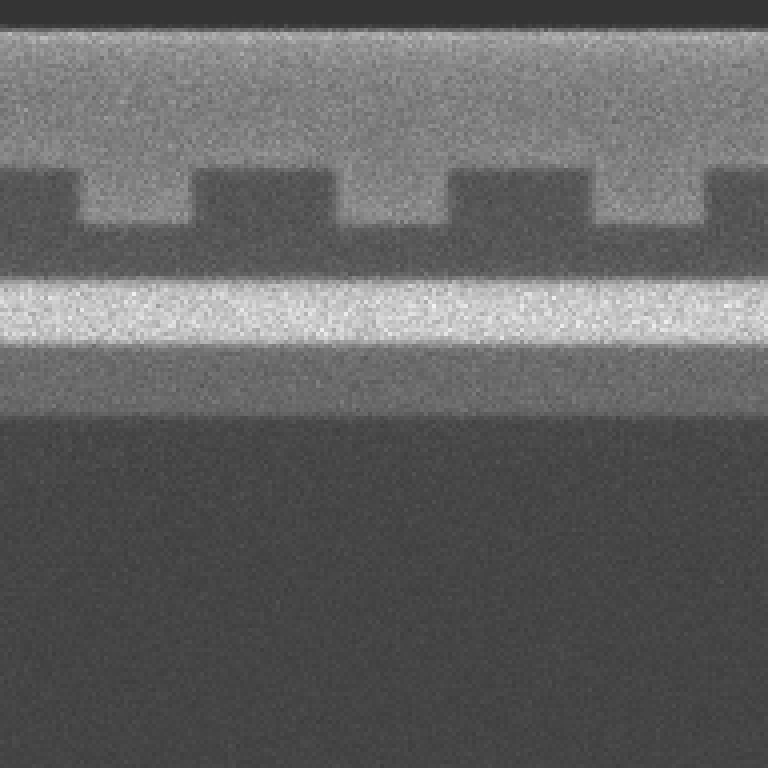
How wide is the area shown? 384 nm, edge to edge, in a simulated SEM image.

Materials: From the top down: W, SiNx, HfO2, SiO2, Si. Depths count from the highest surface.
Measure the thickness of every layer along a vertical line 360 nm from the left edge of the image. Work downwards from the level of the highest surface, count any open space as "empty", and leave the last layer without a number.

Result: W 68, SiNx 56, HfO2 32, SiO2 36, Si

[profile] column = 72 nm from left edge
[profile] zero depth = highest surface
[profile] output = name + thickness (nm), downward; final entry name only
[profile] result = W 96, SiNx 28, HfO2 32, SiO2 36, Si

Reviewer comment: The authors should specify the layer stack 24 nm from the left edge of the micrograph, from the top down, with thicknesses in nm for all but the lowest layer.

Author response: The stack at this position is W 68, SiNx 56, HfO2 32, SiO2 36, Si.